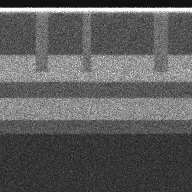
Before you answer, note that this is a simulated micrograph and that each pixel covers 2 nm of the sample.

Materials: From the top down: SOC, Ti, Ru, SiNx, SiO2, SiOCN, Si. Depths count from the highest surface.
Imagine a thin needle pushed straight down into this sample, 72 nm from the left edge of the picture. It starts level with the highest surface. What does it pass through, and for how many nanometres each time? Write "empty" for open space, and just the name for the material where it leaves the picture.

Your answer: SOC 128, Ru 20, SiNx 32, SiO2 44, SiOCN 28, Si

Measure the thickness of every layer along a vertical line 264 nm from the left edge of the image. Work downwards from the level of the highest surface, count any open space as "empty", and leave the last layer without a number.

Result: SOC 8, Ti 86, Ru 54, SiNx 32, SiO2 44, SiOCN 28, Si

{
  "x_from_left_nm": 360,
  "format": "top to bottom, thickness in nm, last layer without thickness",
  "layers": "SOC 8, Ti 86, Ru 54, SiNx 32, SiO2 44, SiOCN 28, Si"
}